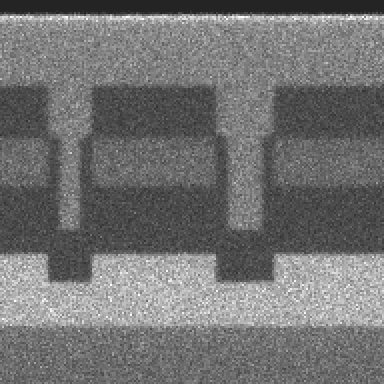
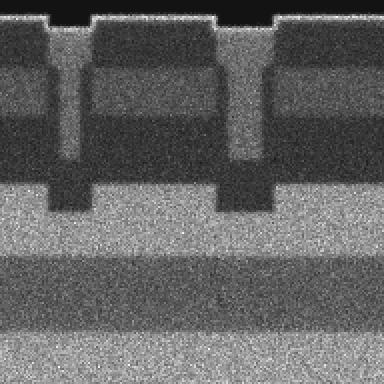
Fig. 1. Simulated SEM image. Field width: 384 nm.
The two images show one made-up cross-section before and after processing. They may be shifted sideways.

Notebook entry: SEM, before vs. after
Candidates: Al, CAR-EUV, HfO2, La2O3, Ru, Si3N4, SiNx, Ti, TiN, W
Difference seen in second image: W removed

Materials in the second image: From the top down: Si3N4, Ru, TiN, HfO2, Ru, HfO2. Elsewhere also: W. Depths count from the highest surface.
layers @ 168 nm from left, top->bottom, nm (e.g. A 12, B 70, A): Si3N4 52, Ru 48, TiN 68, HfO2 72, Ru 76, HfO2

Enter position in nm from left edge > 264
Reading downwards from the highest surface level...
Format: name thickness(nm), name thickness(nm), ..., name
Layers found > empty 12, W 40, Si3N4 144, HfO2 44, Ru 76, HfO2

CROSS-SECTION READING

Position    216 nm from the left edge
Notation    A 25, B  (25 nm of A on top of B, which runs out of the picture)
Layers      empty 12, W 36, Si3N4 148, HfO2 44, Ru 76, HfO2